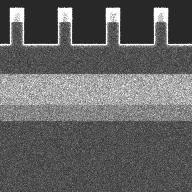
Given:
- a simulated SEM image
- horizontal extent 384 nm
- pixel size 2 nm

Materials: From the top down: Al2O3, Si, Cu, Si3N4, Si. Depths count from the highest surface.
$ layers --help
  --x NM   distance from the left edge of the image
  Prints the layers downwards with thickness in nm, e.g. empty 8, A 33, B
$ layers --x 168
empty 72, Si 60, Cu 62, Si3N4 32, Si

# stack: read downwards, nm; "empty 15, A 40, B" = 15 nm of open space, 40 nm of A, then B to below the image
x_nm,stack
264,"empty 72, Si 60, Cu 62, Si3N4 32, Si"